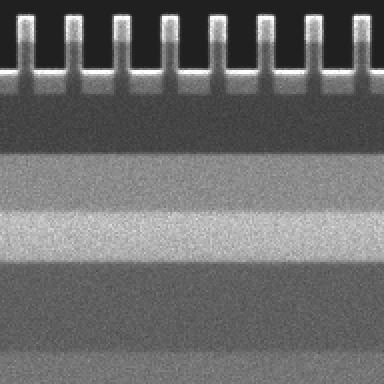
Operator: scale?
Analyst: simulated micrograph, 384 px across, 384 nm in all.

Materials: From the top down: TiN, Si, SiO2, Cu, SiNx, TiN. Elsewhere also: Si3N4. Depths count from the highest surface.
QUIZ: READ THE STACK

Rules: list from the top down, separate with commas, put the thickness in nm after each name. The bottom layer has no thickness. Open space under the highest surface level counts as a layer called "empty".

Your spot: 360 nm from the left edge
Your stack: TiN 26, Si 112, SiO2 58, Cu 50, SiNx 90, TiN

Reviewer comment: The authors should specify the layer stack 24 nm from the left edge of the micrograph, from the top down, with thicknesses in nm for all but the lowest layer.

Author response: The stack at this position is TiN 26, Si 112, SiO2 58, Cu 50, SiNx 90, TiN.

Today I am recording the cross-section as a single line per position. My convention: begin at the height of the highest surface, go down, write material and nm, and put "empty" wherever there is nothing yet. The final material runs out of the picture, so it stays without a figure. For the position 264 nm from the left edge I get TiN 26, Si 112, SiO2 58, Cu 50, SiNx 90, TiN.